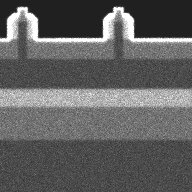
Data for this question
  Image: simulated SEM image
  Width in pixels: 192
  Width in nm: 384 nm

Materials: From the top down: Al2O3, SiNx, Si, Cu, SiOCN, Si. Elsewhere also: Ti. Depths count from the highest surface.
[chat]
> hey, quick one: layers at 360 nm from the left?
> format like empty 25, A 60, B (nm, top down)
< empty 62, SiNx 40, Si 60, Cu 36, SiOCN 66, Si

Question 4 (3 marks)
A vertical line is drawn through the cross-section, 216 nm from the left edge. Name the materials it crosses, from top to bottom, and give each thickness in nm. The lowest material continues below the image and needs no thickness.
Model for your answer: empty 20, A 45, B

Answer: empty 14, Al2O3 48, SiNx 40, Si 60, Cu 36, SiOCN 66, Si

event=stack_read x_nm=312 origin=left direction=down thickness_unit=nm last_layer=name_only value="empty 62, SiNx 40, Si 60, Cu 36, SiOCN 66, Si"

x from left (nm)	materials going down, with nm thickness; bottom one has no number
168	empty 62, SiNx 40, Si 60, Cu 36, SiOCN 66, Si